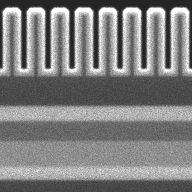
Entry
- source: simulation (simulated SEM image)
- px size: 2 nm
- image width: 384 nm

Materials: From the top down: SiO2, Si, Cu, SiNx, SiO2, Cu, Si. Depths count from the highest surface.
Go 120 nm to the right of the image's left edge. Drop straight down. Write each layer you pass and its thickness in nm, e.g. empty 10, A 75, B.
SiO2 14, Si 182, Cu 30, SiNx 40, SiO2 52, Cu 26, Si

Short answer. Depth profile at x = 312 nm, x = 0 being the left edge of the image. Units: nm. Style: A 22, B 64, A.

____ SiO2 14, Si 182, Cu 30, SiNx 40, SiO2 52, Cu 26, Si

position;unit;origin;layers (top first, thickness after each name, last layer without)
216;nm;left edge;SiO2 14, Si 182, Cu 30, SiNx 40, SiO2 52, Cu 26, Si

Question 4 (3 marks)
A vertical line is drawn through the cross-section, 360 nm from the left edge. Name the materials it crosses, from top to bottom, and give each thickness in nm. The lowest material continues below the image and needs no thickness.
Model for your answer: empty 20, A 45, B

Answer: SiO2 14, Si 182, Cu 30, SiNx 40, SiO2 52, Cu 26, Si